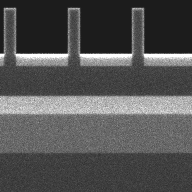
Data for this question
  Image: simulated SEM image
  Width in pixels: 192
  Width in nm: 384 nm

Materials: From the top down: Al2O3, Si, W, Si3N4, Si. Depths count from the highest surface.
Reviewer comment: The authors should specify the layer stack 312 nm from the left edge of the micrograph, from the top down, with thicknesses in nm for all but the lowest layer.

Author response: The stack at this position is empty 92, Al2O3 24, Si 60, W 36, Si3N4 78, Si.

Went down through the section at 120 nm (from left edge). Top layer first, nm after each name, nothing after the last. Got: empty 92, Al2O3 24, Si 60, W 36, Si3N4 78, Si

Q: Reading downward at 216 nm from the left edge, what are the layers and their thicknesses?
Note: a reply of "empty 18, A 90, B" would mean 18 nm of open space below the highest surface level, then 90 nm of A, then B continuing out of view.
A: empty 92, Al2O3 24, Si 60, W 36, Si3N4 78, Si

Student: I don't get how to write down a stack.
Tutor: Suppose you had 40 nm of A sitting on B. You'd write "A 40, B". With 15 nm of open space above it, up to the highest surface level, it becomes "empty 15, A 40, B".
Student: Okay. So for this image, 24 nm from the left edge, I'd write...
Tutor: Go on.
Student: Si 176, W 36, Si3N4 78, Si